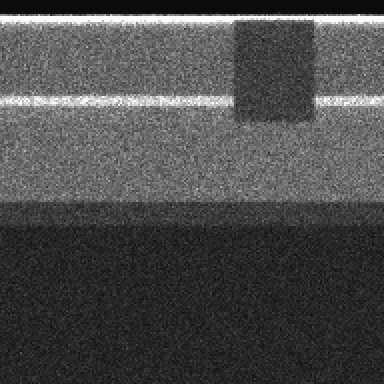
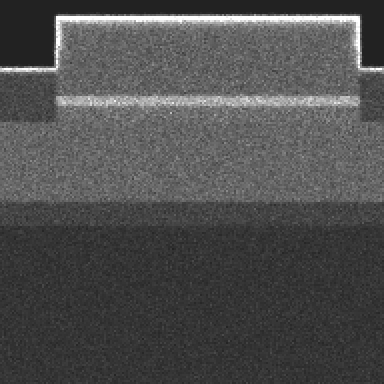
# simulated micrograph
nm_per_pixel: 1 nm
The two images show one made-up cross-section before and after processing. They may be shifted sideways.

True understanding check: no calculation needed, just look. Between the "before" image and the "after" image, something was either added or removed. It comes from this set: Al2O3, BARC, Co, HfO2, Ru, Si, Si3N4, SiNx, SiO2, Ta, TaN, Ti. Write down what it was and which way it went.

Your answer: SiNx (removed)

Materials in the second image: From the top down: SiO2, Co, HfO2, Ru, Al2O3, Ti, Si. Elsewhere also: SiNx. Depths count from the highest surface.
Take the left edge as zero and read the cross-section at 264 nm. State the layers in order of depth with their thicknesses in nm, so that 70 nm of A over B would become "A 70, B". SiO2 32, Co 48, HfO2 10, Ru 16, Al2O3 80, Ti 24, Si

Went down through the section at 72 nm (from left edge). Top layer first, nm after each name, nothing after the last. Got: SiO2 32, Co 48, HfO2 10, Ru 16, Al2O3 80, Ti 24, Si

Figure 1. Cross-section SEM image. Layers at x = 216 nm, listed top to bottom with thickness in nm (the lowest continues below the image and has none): SiO2 32, Co 48, HfO2 10, Ru 16, Al2O3 80, Ti 24, Si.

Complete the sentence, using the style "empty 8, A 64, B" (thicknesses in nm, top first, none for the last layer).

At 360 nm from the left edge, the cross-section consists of empty 52, SiNx 54, Al2O3 80, Ti 24, Si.